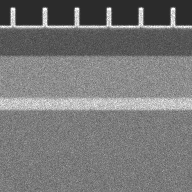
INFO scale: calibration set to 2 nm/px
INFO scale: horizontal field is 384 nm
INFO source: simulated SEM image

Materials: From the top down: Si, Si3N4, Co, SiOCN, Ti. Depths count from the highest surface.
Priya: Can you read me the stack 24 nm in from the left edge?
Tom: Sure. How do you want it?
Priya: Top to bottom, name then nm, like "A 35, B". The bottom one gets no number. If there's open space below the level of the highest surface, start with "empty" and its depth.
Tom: Si 96, Si3N4 84, Co 24, SiOCN 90, Ti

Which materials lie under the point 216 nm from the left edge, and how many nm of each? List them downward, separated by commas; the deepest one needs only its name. Si 96, Si3N4 84, Co 24, SiOCN 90, Ti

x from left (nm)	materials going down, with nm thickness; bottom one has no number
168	empty 36, Si 60, Si3N4 84, Co 24, SiOCN 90, Ti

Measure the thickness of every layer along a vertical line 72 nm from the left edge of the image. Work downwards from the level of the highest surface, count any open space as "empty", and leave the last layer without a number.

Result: empty 36, Si 60, Si3N4 84, Co 24, SiOCN 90, Ti